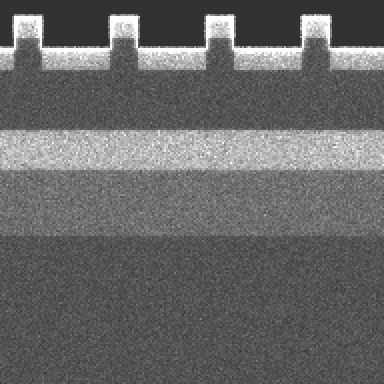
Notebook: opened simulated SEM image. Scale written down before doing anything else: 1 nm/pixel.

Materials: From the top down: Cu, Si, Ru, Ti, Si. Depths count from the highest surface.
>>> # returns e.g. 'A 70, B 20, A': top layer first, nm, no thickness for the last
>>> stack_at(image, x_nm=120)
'Cu 22, Si 92, Ru 40, Ti 66, Si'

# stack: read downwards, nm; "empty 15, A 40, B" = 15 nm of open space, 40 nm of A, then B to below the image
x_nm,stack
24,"Cu 22, Si 92, Ru 40, Ti 66, Si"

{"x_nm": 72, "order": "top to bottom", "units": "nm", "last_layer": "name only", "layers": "empty 32, Cu 22, Si 60, Ru 40, Ti 66, Si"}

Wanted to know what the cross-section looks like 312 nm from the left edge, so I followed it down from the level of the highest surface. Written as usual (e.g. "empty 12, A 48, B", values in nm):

Cu 22, Si 92, Ru 40, Ti 66, Si